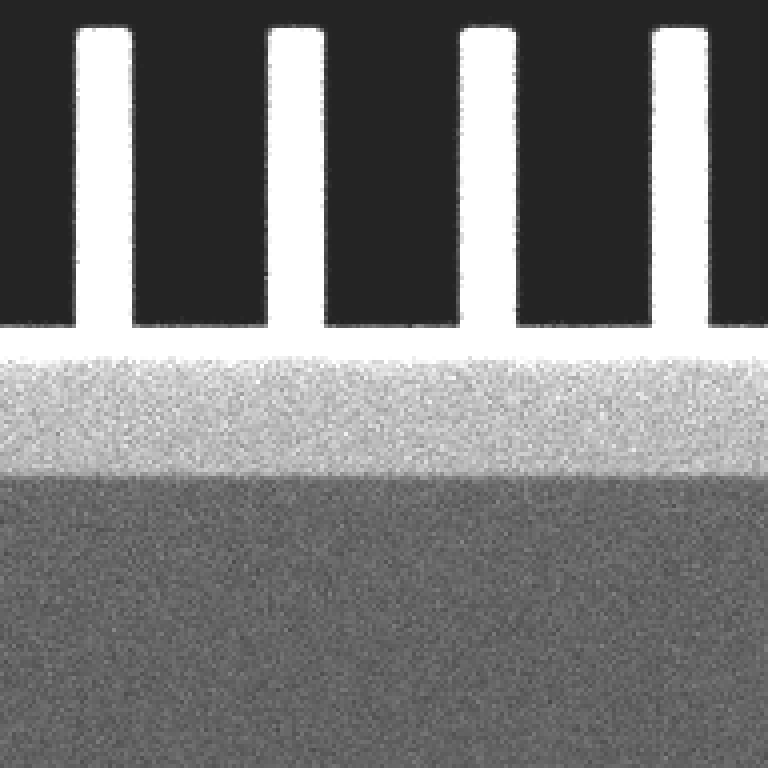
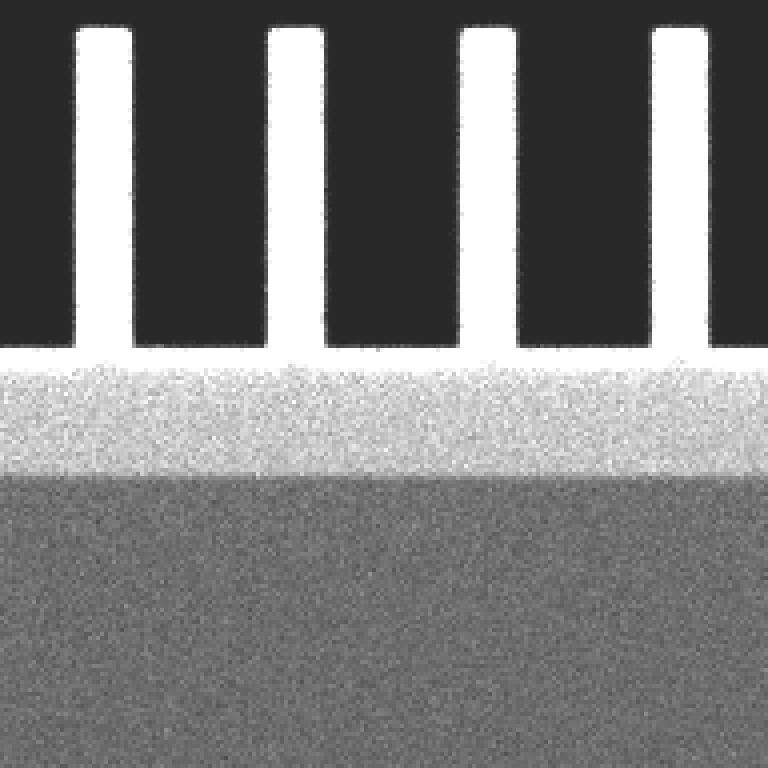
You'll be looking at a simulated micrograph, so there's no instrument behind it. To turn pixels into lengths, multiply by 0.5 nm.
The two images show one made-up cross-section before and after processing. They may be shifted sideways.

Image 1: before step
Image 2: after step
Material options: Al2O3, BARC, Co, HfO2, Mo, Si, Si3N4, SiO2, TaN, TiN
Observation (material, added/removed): HfO2, removed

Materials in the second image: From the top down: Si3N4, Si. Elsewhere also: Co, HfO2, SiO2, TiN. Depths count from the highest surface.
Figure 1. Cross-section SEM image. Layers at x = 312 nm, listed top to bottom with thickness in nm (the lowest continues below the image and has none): empty 160, Si3N4 62, Si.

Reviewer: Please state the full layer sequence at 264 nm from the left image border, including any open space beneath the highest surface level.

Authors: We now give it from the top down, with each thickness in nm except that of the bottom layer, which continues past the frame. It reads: empty 160, Si3N4 62, Si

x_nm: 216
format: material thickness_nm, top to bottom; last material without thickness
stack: empty 160, Si3N4 62, Si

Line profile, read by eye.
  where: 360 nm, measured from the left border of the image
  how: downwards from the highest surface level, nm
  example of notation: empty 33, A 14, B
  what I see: empty 160, Si3N4 62, Si